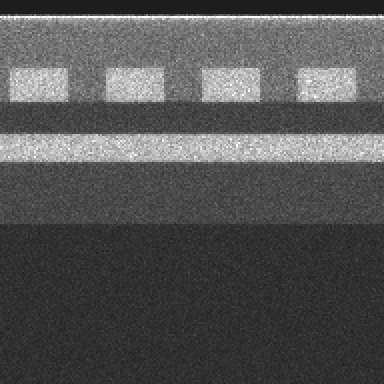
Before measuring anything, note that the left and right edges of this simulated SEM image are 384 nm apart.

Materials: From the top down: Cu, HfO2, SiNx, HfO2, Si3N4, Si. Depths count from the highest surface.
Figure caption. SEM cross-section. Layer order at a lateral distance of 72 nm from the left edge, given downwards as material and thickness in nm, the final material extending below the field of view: Cu 86, SiNx 32, HfO2 28, Si3N4 62, Si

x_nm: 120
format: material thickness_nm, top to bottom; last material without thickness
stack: Cu 52, HfO2 34, SiNx 32, HfO2 28, Si3N4 62, Si